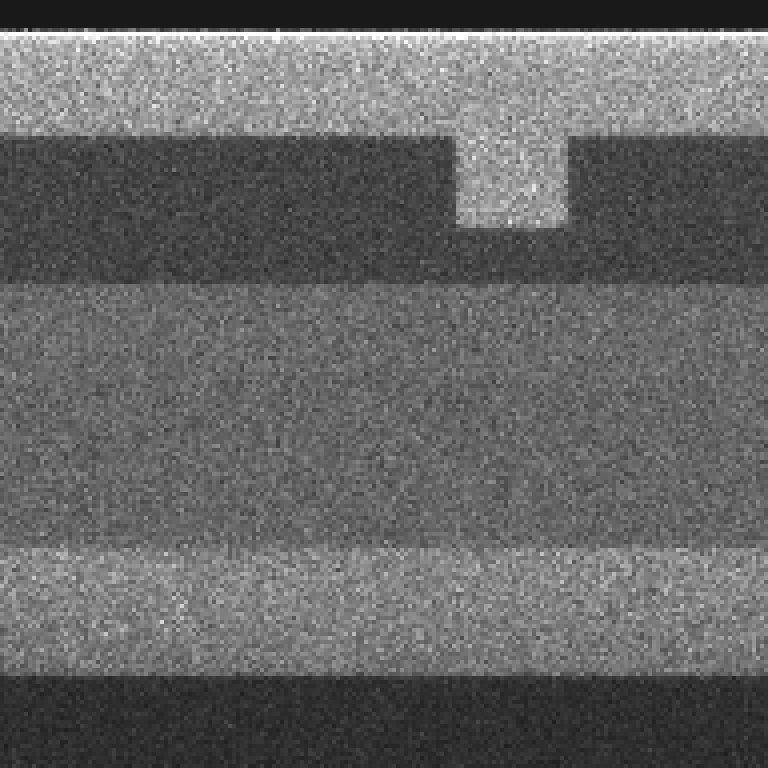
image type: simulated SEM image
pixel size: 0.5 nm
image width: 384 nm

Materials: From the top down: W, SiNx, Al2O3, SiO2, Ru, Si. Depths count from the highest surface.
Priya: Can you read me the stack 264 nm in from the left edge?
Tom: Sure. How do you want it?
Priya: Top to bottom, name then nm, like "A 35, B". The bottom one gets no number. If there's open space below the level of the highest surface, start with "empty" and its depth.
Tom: W 98, SiNx 28, Al2O3 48, SiO2 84, Ru 64, Si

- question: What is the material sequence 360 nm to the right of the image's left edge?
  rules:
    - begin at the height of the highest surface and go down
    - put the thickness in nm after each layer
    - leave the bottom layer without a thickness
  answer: W 52, SiNx 74, Al2O3 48, SiO2 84, Ru 64, Si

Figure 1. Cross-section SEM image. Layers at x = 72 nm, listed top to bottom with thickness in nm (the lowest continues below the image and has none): W 52, SiNx 74, Al2O3 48, SiO2 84, Ru 64, Si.